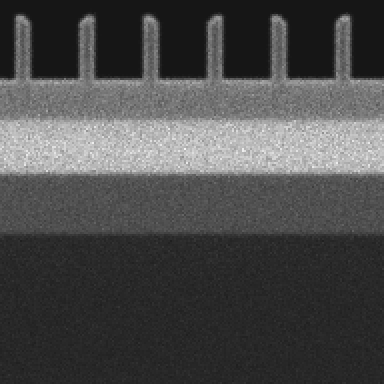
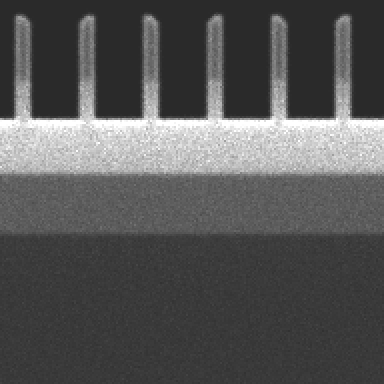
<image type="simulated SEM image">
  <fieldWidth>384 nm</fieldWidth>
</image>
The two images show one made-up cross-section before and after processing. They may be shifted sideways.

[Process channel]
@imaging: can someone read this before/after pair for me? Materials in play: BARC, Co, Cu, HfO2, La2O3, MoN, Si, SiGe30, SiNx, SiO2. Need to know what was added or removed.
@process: Co removed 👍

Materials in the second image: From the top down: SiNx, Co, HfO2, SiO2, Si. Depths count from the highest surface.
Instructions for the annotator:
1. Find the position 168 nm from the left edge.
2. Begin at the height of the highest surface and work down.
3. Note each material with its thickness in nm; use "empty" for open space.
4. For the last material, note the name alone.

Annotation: empty 104, HfO2 54, SiO2 60, Si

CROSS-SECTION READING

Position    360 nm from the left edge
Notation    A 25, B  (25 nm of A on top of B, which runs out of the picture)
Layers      empty 104, HfO2 54, SiO2 60, Si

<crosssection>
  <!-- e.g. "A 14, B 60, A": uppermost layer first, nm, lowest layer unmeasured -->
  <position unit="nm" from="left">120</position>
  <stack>empty 104, HfO2 54, SiO2 60, Si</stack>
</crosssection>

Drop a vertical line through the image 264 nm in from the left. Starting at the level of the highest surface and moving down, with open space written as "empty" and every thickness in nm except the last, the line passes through empty 104, HfO2 54, SiO2 60, Si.